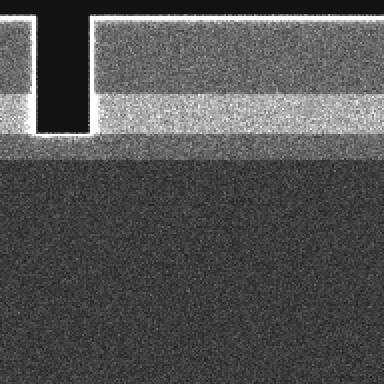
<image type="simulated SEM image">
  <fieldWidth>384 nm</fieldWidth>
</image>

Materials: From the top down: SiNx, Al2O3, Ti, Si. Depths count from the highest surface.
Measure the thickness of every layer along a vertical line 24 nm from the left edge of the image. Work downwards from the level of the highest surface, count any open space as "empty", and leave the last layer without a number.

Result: SiNx 78, Al2O3 40, Ti 26, Si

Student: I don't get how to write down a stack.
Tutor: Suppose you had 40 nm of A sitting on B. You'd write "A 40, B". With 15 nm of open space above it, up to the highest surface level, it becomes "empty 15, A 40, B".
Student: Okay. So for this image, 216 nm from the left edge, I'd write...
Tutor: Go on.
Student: SiNx 78, Al2O3 40, Ti 26, Si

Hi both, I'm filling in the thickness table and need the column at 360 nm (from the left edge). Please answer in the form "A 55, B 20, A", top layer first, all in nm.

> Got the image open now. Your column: SiNx 78, Al2O3 40, Ti 26, Si